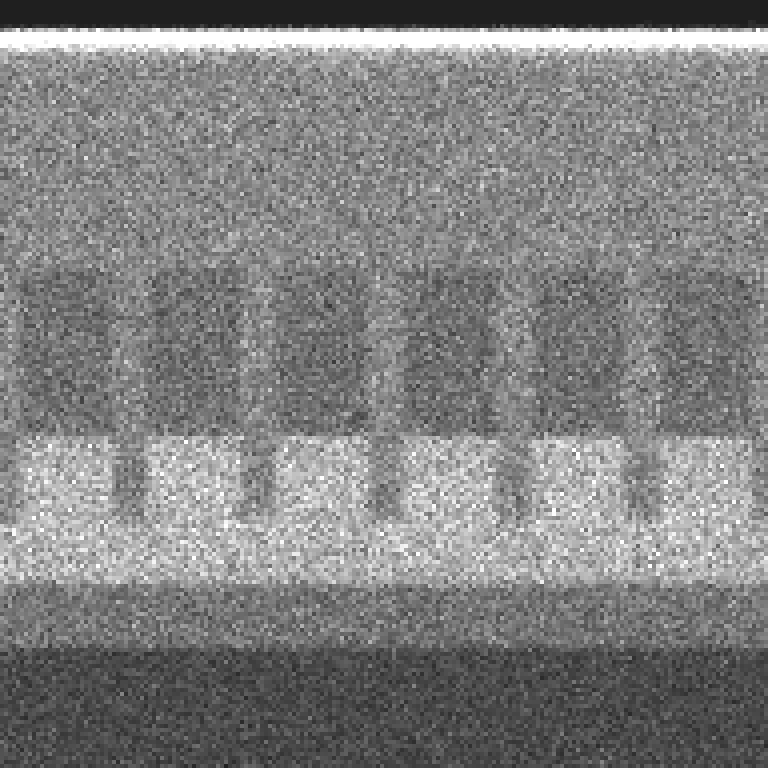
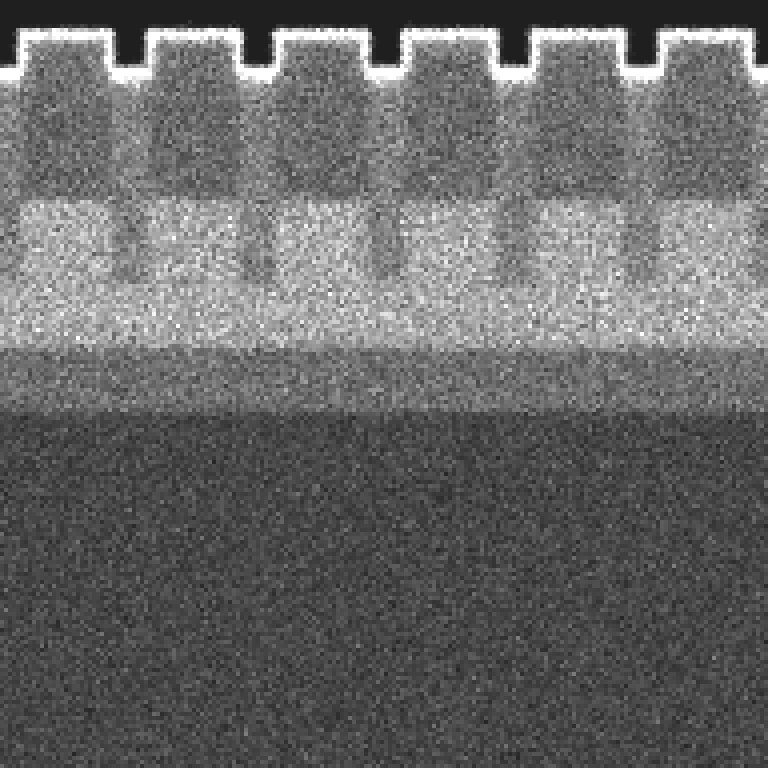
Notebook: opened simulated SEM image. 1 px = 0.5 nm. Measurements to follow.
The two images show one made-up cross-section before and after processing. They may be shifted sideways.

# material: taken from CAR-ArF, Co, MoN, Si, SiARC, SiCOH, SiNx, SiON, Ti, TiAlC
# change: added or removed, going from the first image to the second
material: SiARC
change: removed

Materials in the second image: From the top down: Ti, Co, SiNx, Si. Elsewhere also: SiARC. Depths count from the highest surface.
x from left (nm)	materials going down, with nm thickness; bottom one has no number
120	empty 18, SiARC 108, Co 32, SiNx 32, Si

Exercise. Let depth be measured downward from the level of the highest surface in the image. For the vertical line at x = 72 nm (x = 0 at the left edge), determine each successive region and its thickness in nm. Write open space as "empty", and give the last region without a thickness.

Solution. empty 18, SiARC 108, Co 32, SiNx 32, Si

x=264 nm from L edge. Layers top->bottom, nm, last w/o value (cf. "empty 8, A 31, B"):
empty 18, SiARC 108, Co 32, SiNx 32, Si